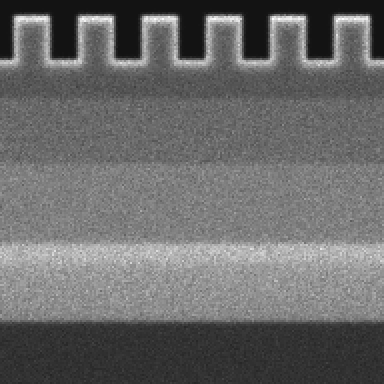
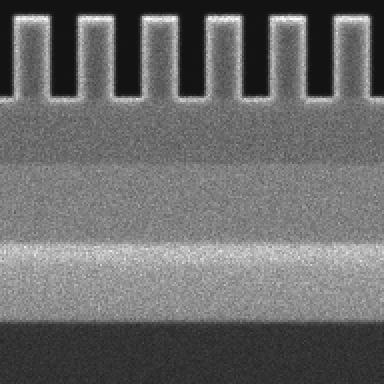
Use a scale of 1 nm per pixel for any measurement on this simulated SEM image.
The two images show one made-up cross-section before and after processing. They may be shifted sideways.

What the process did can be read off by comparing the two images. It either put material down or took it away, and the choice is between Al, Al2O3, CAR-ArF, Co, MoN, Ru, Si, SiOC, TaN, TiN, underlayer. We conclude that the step removed underlayer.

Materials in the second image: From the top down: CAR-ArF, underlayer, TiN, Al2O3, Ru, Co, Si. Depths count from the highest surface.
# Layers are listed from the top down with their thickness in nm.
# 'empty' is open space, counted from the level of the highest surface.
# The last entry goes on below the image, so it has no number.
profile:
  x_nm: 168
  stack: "CAR-ArF 44, underlayer 38, TiN 66, Al2O3 80, Ru 20, Co 58, Si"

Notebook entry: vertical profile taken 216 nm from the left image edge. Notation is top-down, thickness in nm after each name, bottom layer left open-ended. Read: CAR-ArF 44, underlayer 38, TiN 66, Al2O3 80, Ru 20, Co 58, Si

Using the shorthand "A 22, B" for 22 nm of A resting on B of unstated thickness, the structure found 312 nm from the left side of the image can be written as empty 82, TiN 66, Al2O3 80, Ru 20, Co 58, Si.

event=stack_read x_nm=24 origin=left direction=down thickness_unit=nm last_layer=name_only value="CAR-ArF 44, underlayer 38, TiN 66, Al2O3 80, Ru 20, Co 58, Si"